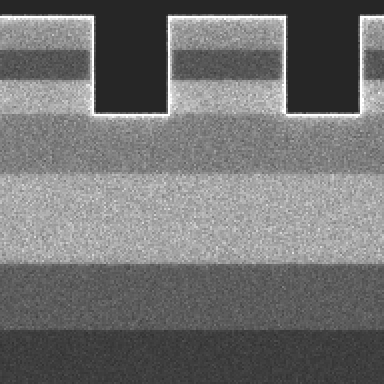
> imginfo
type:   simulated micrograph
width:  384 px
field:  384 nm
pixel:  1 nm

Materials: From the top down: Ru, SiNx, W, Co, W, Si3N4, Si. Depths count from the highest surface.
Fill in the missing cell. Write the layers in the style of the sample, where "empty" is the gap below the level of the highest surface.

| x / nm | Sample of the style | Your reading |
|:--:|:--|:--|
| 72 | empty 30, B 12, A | Ru 34, SiNx 30, W 34, Co 60, W 90, Si3N4 66, Si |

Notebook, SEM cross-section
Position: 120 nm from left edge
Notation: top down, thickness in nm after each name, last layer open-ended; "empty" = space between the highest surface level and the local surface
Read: empty 98, Co 60, W 90, Si3N4 66, Si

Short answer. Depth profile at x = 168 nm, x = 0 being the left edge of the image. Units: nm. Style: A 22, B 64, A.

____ Ru 34, SiNx 30, W 34, Co 60, W 90, Si3N4 66, Si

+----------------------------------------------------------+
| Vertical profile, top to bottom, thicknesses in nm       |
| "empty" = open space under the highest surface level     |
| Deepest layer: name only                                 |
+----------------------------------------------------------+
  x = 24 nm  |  Ru 34, SiNx 30, W 34, Co 60, W 90, Si3N4 66, Si